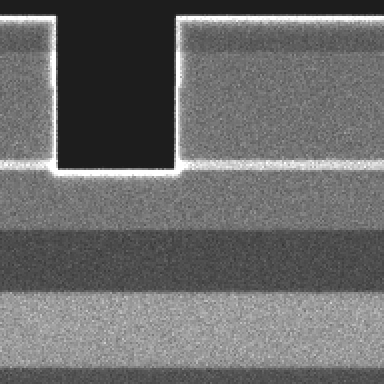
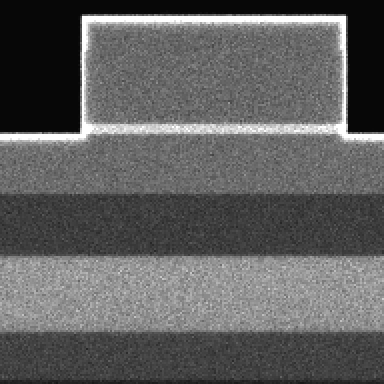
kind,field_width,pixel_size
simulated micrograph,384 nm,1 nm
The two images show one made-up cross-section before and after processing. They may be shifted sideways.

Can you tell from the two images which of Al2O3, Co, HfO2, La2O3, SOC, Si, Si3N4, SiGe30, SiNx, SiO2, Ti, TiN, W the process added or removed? Yes, it removed SOC.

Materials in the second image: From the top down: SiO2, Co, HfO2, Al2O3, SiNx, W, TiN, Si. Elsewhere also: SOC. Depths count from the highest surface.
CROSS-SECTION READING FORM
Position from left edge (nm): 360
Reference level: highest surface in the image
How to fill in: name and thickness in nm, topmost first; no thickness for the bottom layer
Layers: empty 118, Al2O3 60, SiNx 62, W 76, TiN 48, Si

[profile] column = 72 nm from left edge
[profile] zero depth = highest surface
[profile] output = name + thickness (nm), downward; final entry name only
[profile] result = empty 118, Al2O3 60, SiNx 62, W 76, TiN 48, Si